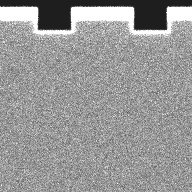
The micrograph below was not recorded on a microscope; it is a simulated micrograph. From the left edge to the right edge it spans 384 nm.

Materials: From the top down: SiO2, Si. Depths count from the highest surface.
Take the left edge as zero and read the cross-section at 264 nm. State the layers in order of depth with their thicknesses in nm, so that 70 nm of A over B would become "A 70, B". SiO2 24, Si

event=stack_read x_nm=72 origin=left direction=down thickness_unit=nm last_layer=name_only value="SiO2 24, Si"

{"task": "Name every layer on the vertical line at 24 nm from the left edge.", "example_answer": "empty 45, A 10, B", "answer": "SiO2 24, Si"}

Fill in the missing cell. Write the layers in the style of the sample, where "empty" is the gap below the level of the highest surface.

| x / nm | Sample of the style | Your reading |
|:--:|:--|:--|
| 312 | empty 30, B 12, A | empty 46, Si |